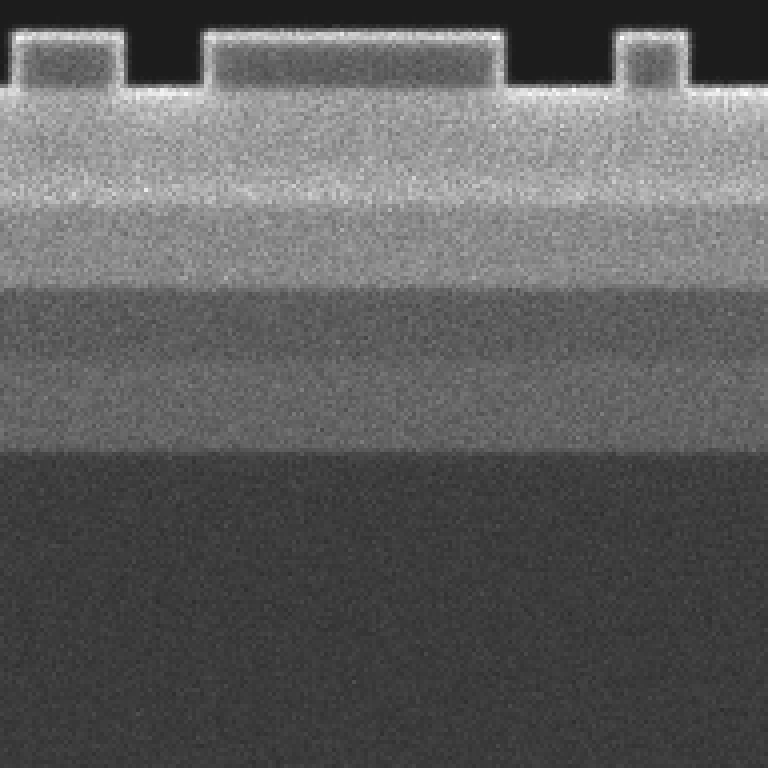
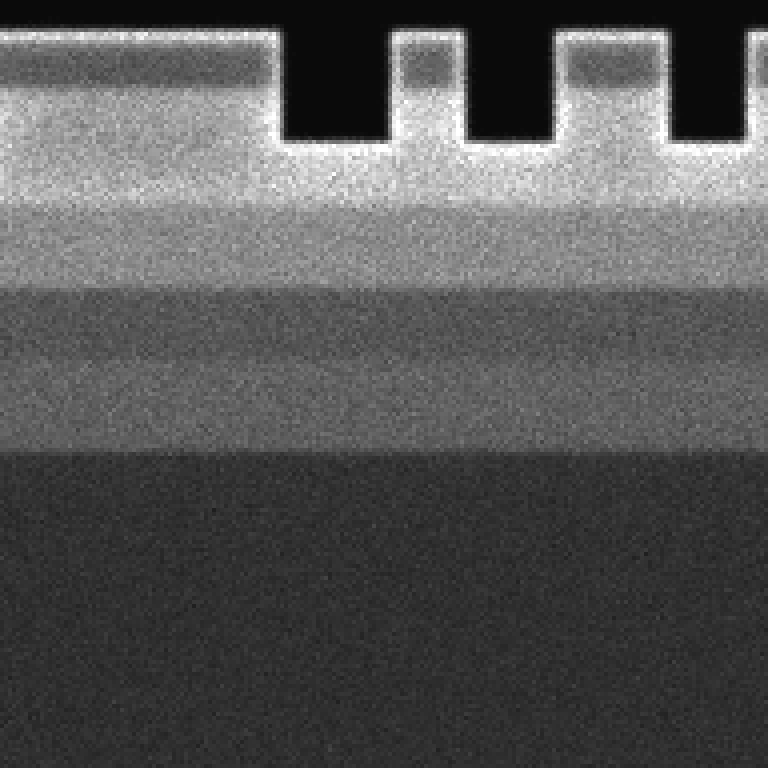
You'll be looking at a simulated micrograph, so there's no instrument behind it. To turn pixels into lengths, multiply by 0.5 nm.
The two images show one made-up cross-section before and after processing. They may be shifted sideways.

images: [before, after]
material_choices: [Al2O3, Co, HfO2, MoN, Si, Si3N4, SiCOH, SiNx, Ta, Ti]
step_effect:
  removed: Co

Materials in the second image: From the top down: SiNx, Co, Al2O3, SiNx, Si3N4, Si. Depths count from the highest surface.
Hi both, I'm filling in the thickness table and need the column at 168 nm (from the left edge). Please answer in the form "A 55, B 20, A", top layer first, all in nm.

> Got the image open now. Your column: empty 56, Co 30, Al2O3 42, SiNx 36, Si3N4 46, Si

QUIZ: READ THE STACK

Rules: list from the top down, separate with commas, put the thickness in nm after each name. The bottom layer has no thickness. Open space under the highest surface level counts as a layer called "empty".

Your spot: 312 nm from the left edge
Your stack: SiNx 28, Co 58, Al2O3 42, SiNx 36, Si3N4 46, Si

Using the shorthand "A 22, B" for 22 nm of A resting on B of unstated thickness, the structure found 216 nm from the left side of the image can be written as SiNx 28, Co 58, Al2O3 42, SiNx 36, Si3N4 46, Si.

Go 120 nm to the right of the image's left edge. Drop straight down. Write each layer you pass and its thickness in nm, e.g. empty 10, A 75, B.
SiNx 28, Co 58, Al2O3 42, SiNx 36, Si3N4 46, Si